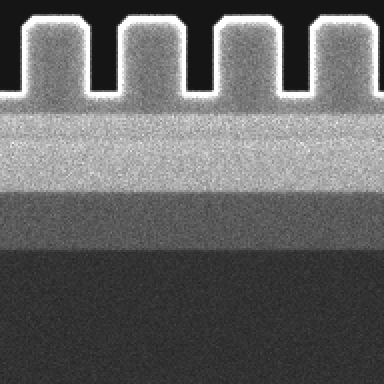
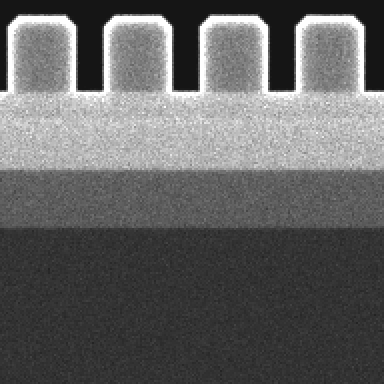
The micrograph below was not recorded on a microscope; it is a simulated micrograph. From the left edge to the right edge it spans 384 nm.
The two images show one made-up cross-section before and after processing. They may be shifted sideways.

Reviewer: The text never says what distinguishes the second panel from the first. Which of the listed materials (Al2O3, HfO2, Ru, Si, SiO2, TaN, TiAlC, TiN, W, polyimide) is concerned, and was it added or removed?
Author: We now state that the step removed Al2O3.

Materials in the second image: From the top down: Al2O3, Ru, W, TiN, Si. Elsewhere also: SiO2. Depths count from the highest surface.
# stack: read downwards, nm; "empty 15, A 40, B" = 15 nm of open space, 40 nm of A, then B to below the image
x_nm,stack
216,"Al2O3 76, Ru 26, W 52, TiN 58, Si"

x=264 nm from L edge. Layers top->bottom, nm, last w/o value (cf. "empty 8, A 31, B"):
empty 8, Al2O3 68, Ru 26, W 52, TiN 58, Si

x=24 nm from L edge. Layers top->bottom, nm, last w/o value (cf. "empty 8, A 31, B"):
Al2O3 76, Ru 26, W 52, TiN 58, Si